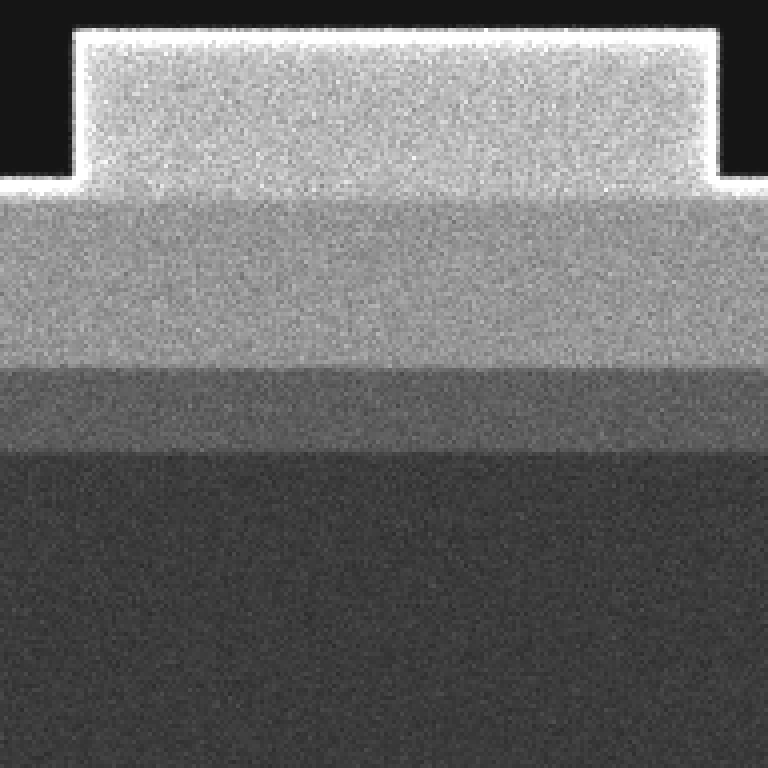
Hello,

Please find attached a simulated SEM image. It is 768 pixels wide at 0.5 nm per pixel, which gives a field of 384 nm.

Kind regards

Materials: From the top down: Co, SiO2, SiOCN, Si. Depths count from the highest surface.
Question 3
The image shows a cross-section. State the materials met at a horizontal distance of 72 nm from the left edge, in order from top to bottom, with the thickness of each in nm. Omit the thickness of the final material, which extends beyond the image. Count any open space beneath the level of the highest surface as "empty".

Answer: Co 84, SiO2 84, SiOCN 42, Si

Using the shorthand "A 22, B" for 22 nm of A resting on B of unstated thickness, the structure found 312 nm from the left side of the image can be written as Co 84, SiO2 84, SiOCN 42, Si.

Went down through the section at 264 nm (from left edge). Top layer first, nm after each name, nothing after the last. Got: Co 84, SiO2 84, SiOCN 42, Si